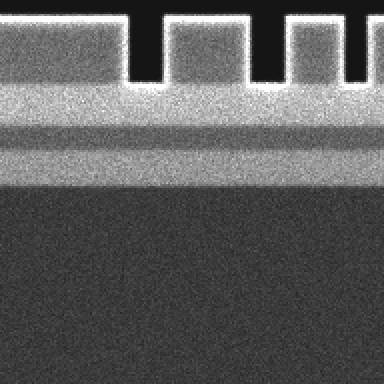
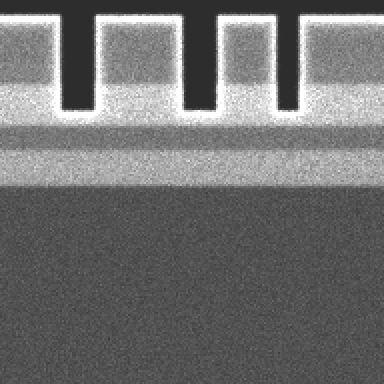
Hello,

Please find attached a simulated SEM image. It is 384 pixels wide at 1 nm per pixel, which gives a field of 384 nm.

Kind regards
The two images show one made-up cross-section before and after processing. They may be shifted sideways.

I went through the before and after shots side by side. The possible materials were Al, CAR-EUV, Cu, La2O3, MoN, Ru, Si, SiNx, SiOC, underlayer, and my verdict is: removed, Ru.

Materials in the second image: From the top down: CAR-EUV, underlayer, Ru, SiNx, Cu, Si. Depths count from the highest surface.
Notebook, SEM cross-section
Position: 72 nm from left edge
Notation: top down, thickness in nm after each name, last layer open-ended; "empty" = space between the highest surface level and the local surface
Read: empty 96, Ru 14, SiNx 24, Cu 36, Si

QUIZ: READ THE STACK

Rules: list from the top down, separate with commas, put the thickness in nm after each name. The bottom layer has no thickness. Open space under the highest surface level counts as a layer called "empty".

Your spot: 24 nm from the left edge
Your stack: CAR-EUV 46, underlayer 22, Ru 42, SiNx 24, Cu 36, Si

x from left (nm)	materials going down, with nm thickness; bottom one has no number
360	CAR-EUV 46, underlayer 22, Ru 42, SiNx 24, Cu 36, Si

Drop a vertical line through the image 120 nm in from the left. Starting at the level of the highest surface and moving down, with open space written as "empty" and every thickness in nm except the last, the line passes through CAR-EUV 46, underlayer 22, Ru 42, SiNx 24, Cu 36, Si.